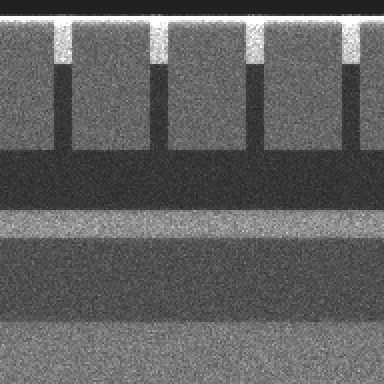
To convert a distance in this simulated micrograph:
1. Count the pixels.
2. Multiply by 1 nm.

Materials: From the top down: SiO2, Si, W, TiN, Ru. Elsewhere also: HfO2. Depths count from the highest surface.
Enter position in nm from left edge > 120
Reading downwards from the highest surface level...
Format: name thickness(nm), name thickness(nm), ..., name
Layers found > SiO2 134, Si 60, W 28, TiN 84, Ru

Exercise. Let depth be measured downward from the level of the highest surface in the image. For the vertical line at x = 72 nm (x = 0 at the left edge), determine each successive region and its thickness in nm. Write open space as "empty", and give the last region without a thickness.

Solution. SiO2 134, Si 60, W 28, TiN 84, Ru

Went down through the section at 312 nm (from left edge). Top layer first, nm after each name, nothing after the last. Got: SiO2 134, Si 60, W 28, TiN 84, Ru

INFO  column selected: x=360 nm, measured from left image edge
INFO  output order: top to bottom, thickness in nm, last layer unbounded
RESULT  SiO2 134, Si 60, W 28, TiN 84, Ru